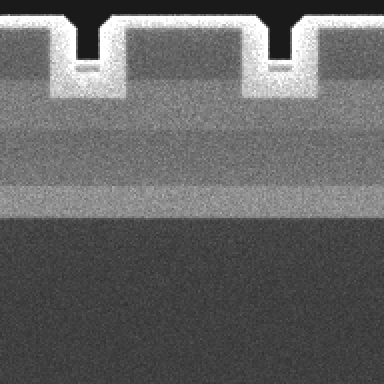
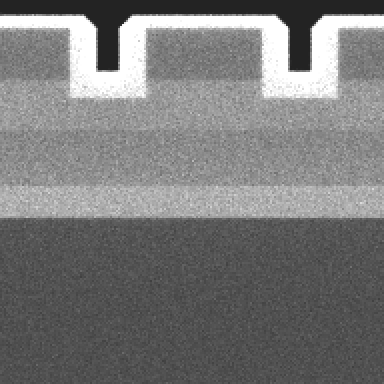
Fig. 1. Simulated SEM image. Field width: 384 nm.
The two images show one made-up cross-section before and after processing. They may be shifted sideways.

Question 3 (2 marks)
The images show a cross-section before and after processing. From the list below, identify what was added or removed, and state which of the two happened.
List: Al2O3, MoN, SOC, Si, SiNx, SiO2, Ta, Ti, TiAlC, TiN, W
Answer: SOC was removed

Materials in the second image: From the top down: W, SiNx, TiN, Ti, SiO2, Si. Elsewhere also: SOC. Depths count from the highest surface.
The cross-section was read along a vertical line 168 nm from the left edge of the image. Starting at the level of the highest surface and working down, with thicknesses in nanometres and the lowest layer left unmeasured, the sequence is W 12, SiNx 52, TiN 50, Ti 56, SiO2 32, Si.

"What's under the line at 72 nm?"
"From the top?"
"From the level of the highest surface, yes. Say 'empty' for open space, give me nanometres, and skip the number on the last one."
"W 82, TiN 32, Ti 56, SiO2 32, Si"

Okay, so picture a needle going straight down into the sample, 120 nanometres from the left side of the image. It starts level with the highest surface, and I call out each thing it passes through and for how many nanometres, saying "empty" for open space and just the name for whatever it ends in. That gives empty 12, W 70, TiN 32, Ti 56, SiO2 32, Si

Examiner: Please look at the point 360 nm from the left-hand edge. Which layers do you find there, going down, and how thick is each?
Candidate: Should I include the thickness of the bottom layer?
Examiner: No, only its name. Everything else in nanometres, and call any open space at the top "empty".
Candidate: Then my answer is W 12, SiNx 52, TiN 50, Ti 56, SiO2 32, Si